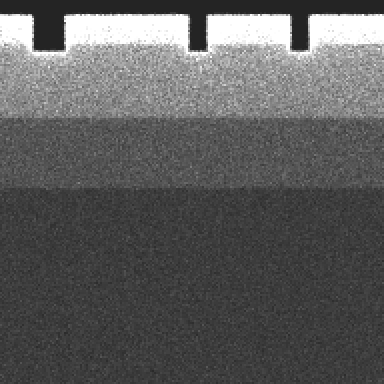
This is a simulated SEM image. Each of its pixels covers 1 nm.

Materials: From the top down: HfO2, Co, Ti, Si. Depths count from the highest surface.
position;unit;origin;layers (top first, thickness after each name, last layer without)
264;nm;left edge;HfO2 28, Co 74, Ti 70, Si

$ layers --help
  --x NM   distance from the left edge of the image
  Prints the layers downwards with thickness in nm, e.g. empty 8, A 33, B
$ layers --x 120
HfO2 28, Co 74, Ti 70, Si